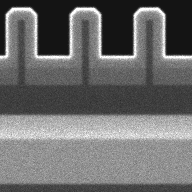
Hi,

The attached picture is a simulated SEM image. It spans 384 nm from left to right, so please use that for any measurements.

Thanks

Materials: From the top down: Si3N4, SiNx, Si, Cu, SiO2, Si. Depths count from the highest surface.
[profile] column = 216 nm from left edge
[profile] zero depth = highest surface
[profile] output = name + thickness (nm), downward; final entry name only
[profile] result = empty 96, Si3N4 24, SiNx 34, Si 60, Cu 48, SiO2 90, Si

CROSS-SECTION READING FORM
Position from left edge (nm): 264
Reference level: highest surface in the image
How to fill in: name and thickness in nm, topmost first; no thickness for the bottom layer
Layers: empty 96, Si3N4 24, SiNx 34, Si 60, Cu 48, SiO2 90, Si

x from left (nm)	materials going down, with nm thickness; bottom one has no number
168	Si3N4 24, Si 190, Cu 48, SiO2 90, Si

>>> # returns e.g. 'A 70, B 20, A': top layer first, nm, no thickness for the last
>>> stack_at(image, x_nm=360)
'empty 96, Si3N4 24, SiNx 34, Si 60, Cu 48, SiO2 90, Si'